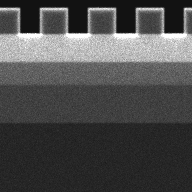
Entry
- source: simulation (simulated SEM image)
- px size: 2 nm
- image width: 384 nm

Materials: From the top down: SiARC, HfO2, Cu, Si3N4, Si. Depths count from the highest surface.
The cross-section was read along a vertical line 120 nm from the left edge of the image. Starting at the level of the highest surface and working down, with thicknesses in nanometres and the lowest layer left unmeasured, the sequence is SiARC 52, HfO2 56, Cu 46, Si3N4 76, Si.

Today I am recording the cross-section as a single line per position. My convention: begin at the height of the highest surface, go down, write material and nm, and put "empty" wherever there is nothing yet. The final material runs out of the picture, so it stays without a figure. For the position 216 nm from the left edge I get SiARC 52, HfO2 56, Cu 46, Si3N4 76, Si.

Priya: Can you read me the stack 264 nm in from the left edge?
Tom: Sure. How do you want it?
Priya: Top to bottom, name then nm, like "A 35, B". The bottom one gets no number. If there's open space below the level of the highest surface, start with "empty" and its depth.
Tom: empty 52, HfO2 56, Cu 46, Si3N4 76, Si